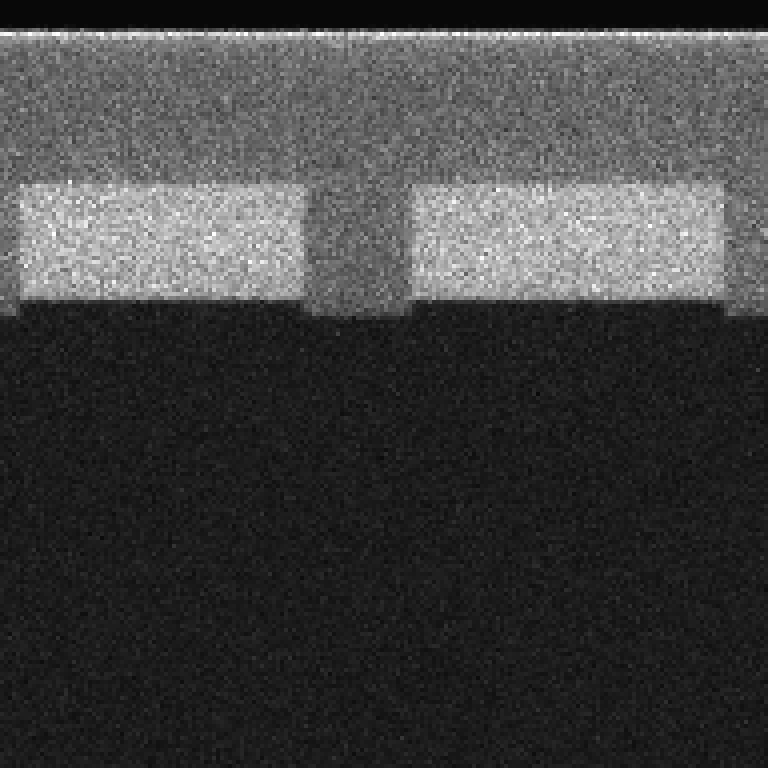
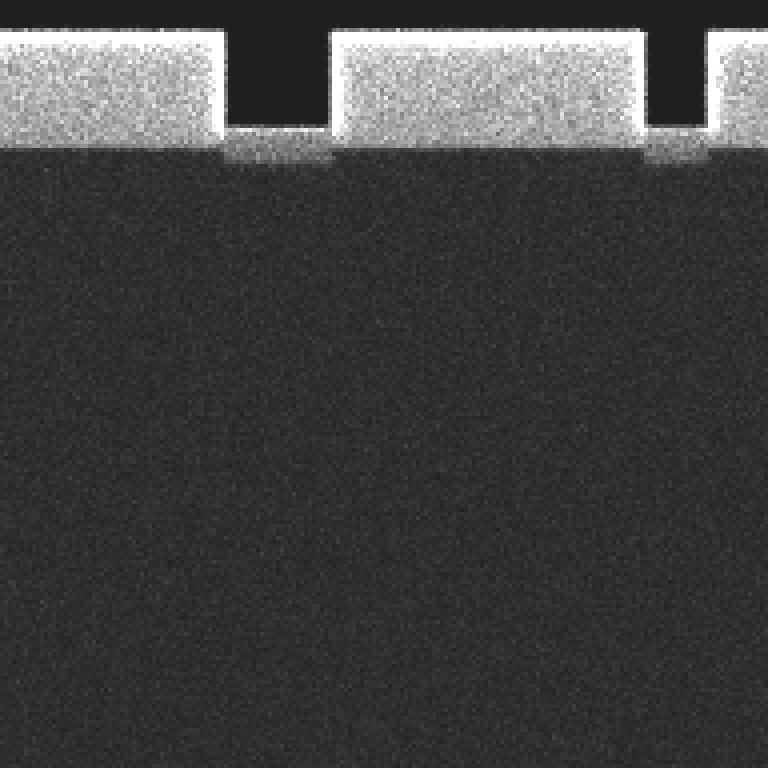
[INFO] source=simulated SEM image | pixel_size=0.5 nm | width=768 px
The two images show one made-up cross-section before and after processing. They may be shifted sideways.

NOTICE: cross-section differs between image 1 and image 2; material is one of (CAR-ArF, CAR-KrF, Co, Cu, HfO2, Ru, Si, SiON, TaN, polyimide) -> removed: Ru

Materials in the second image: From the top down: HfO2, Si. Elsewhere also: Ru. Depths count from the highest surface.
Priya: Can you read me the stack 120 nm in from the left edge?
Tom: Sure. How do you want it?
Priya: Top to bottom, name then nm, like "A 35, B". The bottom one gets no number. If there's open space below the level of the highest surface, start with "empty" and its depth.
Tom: empty 48, Ru 18, Si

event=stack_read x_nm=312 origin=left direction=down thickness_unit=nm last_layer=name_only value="HfO2 58, Si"